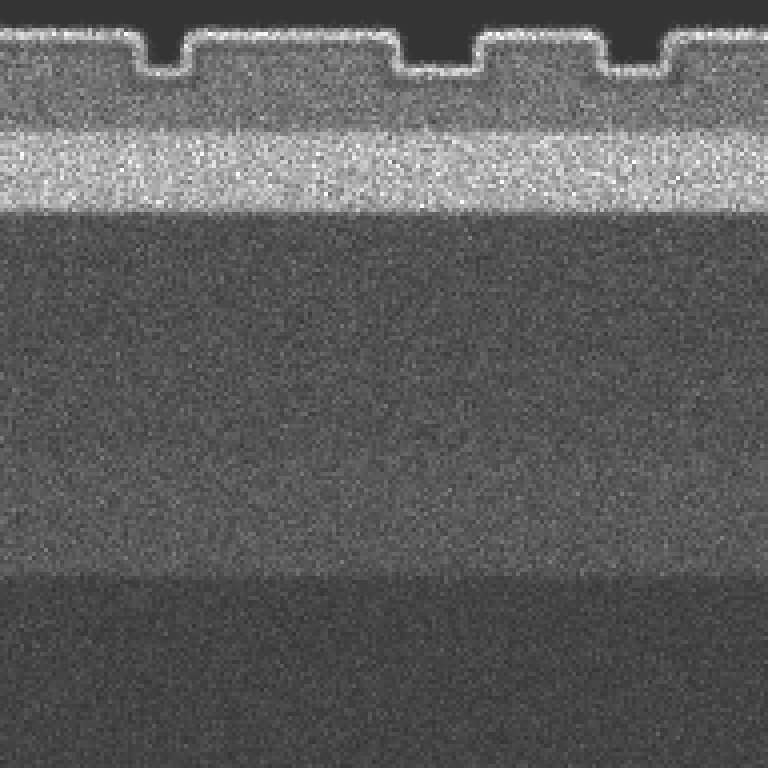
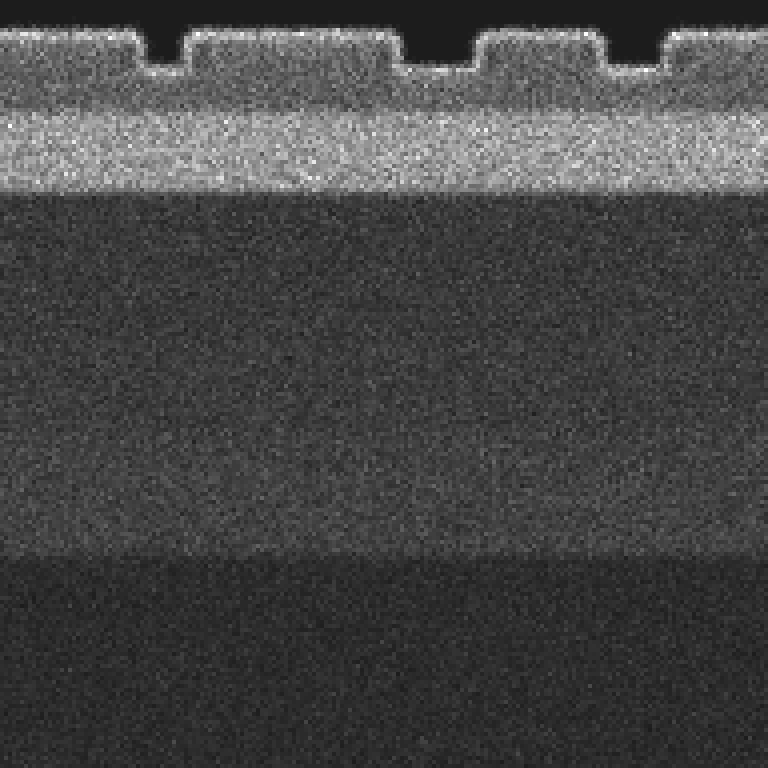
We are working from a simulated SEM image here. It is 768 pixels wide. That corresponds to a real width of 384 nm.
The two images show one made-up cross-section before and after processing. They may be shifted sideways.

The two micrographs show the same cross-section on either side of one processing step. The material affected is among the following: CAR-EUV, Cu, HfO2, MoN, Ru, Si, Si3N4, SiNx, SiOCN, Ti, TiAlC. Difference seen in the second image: SiNx removed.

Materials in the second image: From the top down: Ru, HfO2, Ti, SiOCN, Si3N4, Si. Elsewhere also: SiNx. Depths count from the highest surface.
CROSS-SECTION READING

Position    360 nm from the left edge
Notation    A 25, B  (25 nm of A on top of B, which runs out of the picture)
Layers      Ru 40, HfO2 40, Ti 74, SiOCN 46, Si3N4 62, Si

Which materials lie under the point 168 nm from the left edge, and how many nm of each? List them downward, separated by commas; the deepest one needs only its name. Ru 40, HfO2 40, Ti 74, SiOCN 46, Si3N4 62, Si